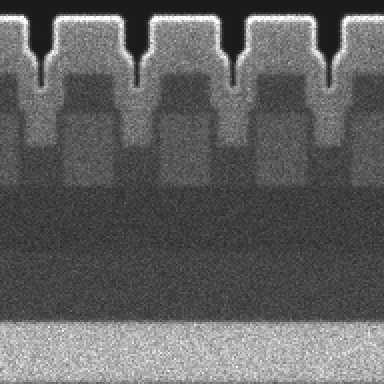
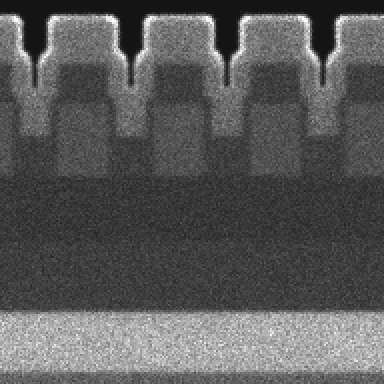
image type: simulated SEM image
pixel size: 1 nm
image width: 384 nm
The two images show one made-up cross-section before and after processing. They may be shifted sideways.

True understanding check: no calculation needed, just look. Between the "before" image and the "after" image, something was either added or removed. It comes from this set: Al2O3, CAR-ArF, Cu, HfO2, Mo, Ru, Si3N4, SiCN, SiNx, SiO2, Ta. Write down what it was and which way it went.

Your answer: Al2O3 (removed)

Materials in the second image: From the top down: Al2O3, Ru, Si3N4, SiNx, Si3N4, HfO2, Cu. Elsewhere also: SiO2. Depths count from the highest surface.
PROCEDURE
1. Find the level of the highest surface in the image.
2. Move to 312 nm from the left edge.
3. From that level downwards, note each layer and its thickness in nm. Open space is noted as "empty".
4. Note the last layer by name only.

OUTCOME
empty 36, Al2O3 36, Ru 48, Si3N4 40, SiNx 66, Si3N4 70, HfO2 60, Cu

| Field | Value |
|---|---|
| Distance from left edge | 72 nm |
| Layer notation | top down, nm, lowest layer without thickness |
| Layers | Ru 48, Si3N4 40, SiO2 72, SiNx 66, Si3N4 70, HfO2 60, Cu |